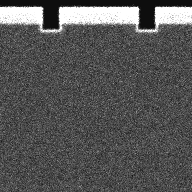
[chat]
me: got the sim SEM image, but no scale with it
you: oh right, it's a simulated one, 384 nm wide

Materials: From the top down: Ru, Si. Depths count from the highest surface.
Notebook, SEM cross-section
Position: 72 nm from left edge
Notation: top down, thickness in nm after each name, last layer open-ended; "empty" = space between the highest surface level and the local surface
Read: Ru 32, Si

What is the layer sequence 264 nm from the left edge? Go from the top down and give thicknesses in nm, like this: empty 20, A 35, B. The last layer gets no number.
Ru 32, Si